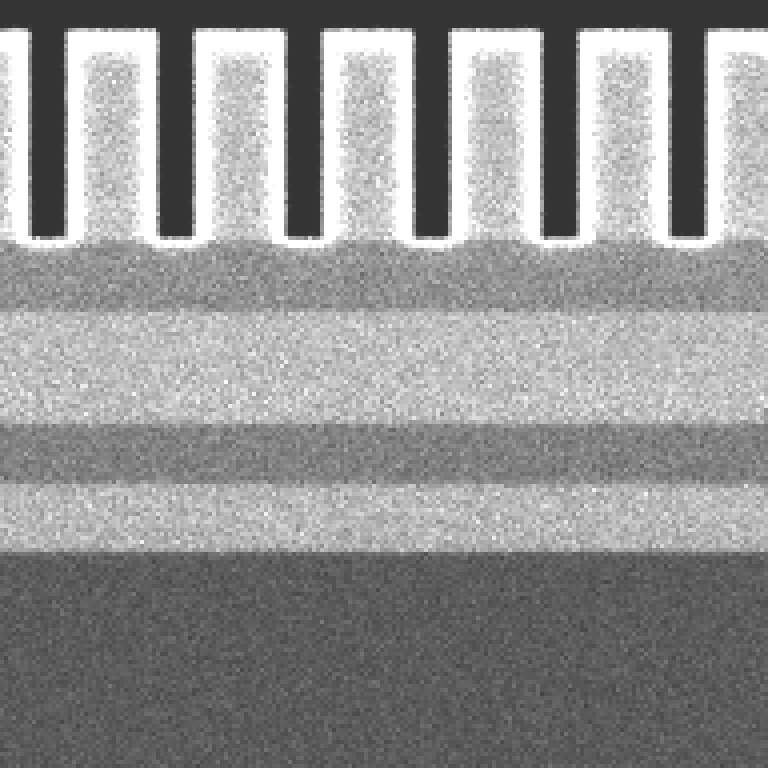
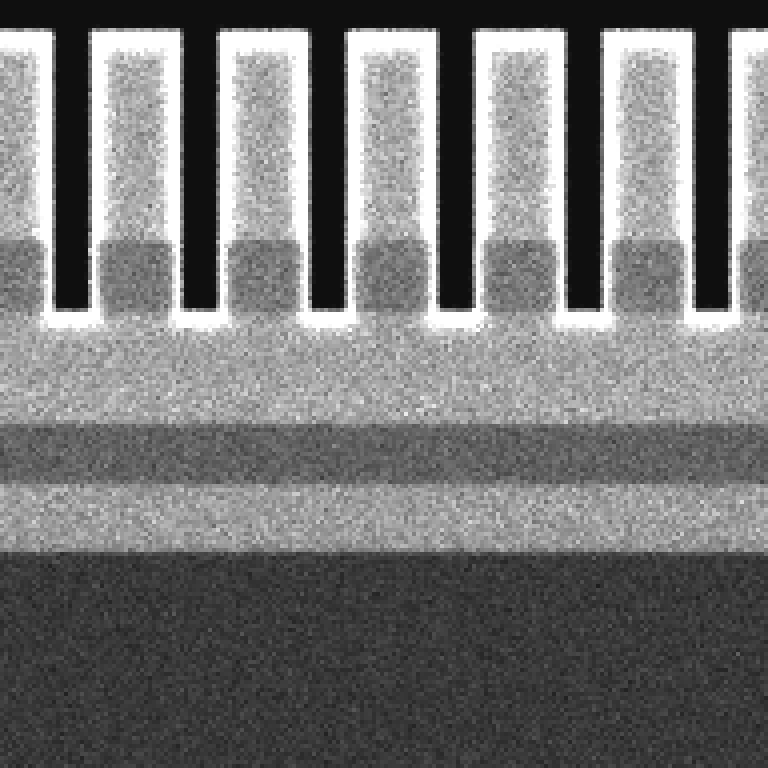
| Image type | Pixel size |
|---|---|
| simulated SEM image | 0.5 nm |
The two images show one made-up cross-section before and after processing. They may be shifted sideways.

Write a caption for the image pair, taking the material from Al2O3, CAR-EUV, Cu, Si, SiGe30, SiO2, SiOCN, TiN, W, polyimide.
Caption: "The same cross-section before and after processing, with TiN removed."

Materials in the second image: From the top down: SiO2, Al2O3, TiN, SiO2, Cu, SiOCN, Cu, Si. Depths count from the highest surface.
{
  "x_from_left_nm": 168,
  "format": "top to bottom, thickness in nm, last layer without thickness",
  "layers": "empty 140, SiO2 36, Cu 20, SiOCN 30, Cu 34, Si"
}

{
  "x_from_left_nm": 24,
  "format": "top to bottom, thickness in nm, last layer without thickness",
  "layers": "SiO2 80, Al2O3 24, TiN 36, SiO2 36, Cu 20, SiOCN 30, Cu 34, Si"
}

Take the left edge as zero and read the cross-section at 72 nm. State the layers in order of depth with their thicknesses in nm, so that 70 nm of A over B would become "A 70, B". SiO2 80, Al2O3 24, TiN 36, SiO2 36, Cu 20, SiOCN 30, Cu 34, Si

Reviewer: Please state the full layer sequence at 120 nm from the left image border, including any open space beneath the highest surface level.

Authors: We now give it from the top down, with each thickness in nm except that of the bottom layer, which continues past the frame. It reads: SiO2 80, Al2O3 24, TiN 36, SiO2 36, Cu 20, SiOCN 30, Cu 34, Si